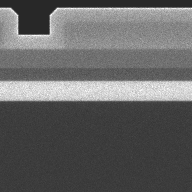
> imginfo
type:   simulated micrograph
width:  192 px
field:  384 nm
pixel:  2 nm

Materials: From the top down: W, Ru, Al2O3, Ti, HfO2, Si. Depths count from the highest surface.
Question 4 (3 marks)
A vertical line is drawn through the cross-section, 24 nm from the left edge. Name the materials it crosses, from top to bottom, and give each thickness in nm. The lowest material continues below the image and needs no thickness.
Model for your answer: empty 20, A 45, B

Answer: empty 4, W 78, Al2O3 38, Ti 26, HfO2 40, Si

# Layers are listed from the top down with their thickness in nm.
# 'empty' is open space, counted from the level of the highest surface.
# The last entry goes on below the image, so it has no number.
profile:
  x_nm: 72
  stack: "empty 54, W 28, Al2O3 38, Ti 26, HfO2 40, Si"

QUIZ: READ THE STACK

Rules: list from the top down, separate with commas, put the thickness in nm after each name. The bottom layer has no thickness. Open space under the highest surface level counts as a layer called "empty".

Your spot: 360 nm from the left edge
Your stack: W 28, Ru 54, Al2O3 38, Ti 26, HfO2 40, Si